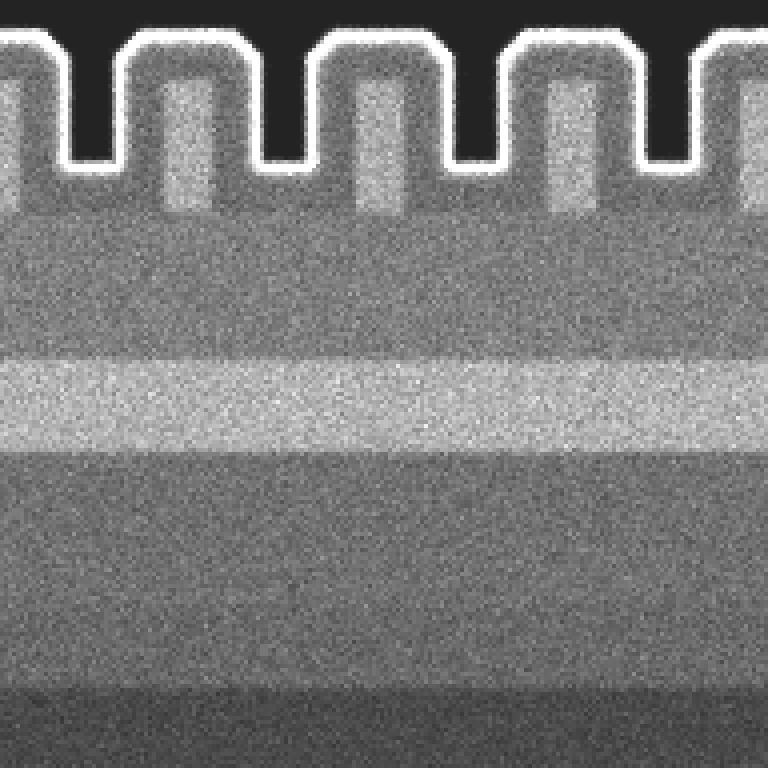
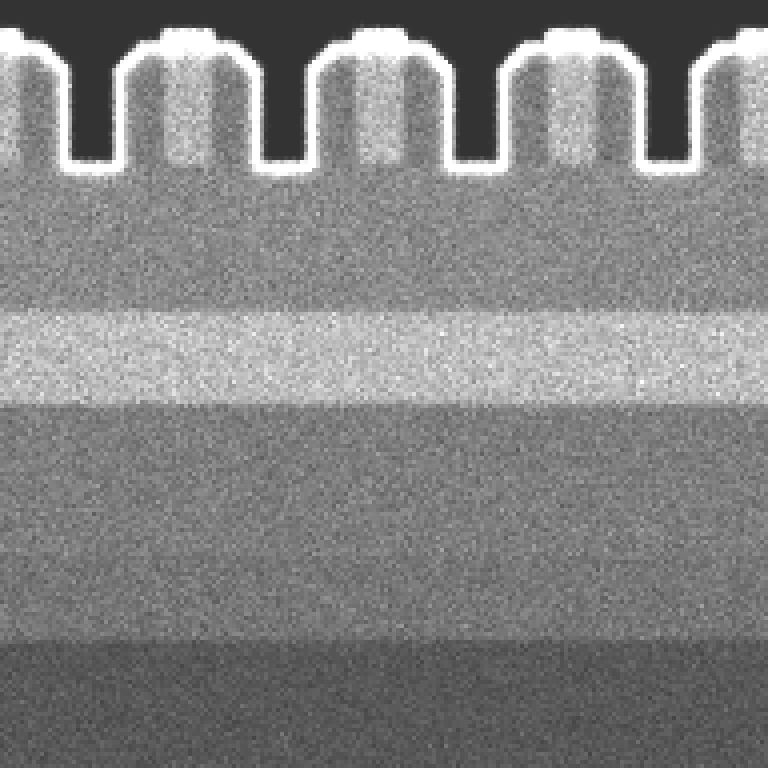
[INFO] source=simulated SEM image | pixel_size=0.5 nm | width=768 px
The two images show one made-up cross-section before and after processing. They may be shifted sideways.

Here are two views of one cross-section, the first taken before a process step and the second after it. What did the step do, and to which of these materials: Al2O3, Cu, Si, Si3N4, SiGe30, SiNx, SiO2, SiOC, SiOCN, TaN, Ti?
It removed SiOCN.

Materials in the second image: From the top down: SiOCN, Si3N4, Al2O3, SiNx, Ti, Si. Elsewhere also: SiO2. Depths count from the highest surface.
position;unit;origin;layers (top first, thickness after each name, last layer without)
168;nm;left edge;empty 6, SiOCN 60, Si3N4 74, Al2O3 46, SiNx 76, Ti 42, Si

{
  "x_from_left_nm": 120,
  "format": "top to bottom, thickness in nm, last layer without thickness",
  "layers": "empty 10, SiOCN 56, Si3N4 74, Al2O3 46, SiNx 76, Ti 42, Si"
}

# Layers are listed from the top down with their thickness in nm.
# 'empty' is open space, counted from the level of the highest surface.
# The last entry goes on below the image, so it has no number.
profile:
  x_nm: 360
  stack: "empty 6, SiOCN 60, Si3N4 74, Al2O3 46, SiNx 76, Ti 42, Si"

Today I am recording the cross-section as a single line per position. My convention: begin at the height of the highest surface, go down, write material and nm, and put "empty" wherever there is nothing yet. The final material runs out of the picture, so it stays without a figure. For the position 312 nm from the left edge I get empty 10, SiOCN 56, Si3N4 74, Al2O3 46, SiNx 76, Ti 42, Si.